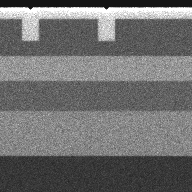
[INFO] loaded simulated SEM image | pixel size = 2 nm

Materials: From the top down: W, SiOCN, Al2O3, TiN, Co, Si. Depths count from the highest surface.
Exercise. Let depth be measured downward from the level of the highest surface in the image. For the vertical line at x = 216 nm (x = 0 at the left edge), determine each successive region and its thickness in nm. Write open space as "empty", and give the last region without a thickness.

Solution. empty 2, W 64, SiOCN 30, Al2O3 50, TiN 60, Co 90, Si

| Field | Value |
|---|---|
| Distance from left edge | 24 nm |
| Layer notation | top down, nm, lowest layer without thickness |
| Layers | W 22, SiOCN 74, Al2O3 50, TiN 60, Co 90, Si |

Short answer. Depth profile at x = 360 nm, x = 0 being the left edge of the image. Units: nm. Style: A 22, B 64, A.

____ W 22, SiOCN 74, Al2O3 50, TiN 60, Co 90, Si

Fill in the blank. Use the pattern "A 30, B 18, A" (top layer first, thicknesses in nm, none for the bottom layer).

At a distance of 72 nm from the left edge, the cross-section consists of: W 66, SiOCN 30, Al2O3 50, TiN 60, Co 90, Si